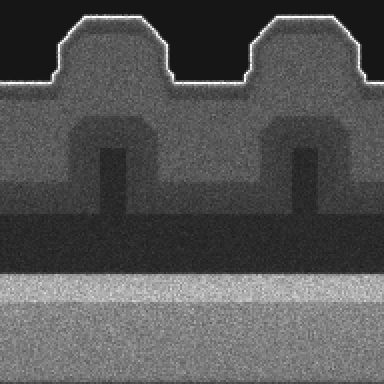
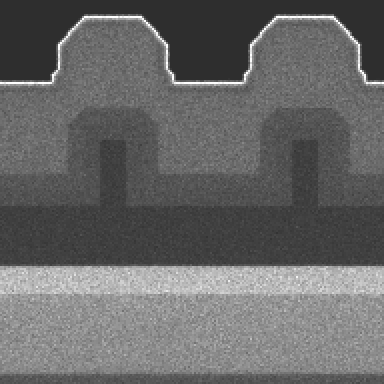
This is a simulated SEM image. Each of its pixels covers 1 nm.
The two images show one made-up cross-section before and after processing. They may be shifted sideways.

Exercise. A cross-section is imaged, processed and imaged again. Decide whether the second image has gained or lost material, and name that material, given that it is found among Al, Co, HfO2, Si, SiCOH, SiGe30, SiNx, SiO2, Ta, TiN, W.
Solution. removed: TiN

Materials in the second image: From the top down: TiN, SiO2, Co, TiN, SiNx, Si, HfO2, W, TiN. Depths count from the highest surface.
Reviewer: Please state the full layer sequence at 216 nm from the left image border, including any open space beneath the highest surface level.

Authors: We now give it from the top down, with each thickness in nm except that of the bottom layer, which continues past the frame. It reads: empty 66, TiN 10, SiO2 34, Co 48, TiN 16, SiNx 16, Si 60, HfO2 28, W 80, TiN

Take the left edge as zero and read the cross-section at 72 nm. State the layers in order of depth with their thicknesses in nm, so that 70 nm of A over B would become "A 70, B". empty 12, TiN 10, SiO2 34, Co 48, TiN 70, SiNx 16, Si 60, HfO2 28, W 80, TiN